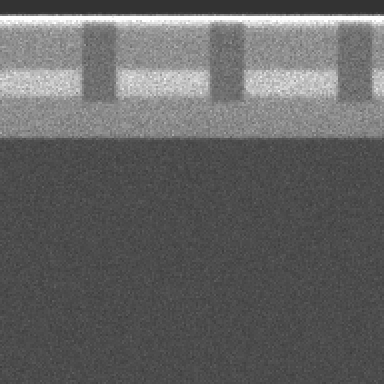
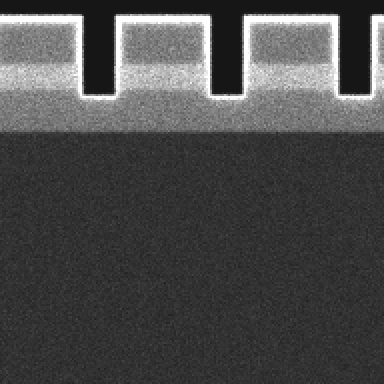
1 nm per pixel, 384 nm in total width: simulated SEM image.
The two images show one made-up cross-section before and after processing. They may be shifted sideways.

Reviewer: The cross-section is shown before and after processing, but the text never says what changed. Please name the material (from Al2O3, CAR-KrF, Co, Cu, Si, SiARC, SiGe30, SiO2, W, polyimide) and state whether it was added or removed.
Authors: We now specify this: SiARC, removed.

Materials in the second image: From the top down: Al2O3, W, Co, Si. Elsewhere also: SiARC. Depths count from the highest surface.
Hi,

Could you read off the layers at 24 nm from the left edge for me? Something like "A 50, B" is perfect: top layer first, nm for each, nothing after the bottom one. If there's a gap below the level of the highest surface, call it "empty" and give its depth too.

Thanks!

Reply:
Al2O3 48, W 26, Co 42, Si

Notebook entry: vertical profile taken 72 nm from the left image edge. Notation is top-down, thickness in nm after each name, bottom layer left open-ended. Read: Al2O3 48, W 26, Co 42, Si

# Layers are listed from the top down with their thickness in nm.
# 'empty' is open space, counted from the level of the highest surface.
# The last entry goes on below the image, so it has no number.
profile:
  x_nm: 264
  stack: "Al2O3 48, W 26, Co 42, Si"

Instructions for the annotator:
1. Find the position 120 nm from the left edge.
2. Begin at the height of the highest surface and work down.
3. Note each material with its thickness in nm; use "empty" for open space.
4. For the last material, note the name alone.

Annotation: Al2O3 48, W 26, Co 42, Si